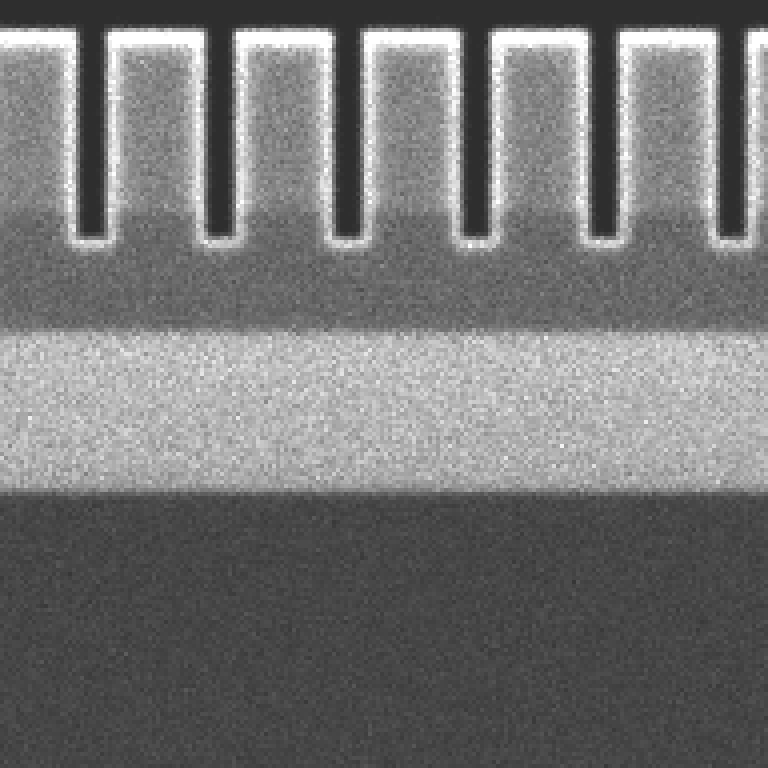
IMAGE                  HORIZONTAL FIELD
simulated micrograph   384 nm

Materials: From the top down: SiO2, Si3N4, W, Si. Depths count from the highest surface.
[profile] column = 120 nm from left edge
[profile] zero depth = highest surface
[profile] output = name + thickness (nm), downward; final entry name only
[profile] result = SiO2 90, Si3N4 60, W 80, Si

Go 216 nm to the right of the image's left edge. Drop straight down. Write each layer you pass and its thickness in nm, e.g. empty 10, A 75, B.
SiO2 90, Si3N4 60, W 80, Si